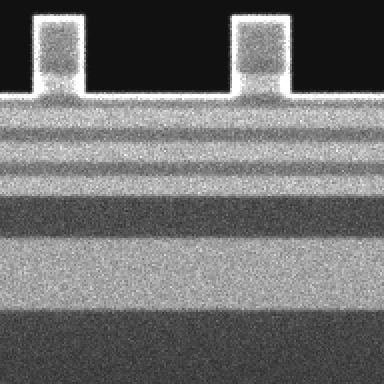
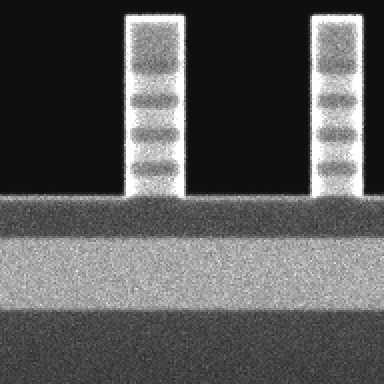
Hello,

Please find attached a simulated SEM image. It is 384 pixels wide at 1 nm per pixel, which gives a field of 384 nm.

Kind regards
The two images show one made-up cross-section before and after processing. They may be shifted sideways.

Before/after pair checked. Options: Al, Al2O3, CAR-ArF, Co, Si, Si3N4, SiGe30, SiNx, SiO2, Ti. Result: removed Al2O3 and SiNx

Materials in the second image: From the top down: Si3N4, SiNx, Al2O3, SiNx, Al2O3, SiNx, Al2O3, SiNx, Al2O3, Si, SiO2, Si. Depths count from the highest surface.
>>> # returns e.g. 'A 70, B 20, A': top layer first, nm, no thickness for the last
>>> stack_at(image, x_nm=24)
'empty 180, Si 42, SiO2 72, Si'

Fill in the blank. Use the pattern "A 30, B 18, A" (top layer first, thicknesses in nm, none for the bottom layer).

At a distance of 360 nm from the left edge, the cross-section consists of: Si3N4 44, SiNx 14, Al2O3 20, SiNx 14, Al2O3 20, SiNx 14, Al2O3 20, SiNx 14, Al2O3 20, Si 42, SiO2 72, Si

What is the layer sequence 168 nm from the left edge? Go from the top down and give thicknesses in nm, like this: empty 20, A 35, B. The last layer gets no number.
Si3N4 44, SiNx 14, Al2O3 20, SiNx 14, Al2O3 20, SiNx 14, Al2O3 20, SiNx 14, Al2O3 20, Si 42, SiO2 72, Si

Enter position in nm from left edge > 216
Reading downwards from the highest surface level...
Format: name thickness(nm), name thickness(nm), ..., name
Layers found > empty 180, Si 42, SiO2 72, Si